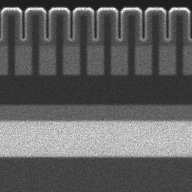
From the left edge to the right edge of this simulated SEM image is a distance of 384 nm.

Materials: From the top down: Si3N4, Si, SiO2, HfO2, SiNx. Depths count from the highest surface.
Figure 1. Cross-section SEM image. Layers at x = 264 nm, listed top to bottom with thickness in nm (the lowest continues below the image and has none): Si3N4 14, Si 180, SiO2 32, HfO2 72, SiNx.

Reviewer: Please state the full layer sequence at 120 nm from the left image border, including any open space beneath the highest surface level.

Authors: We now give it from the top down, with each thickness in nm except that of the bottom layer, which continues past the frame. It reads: Si3N4 14, Si 180, SiO2 32, HfO2 72, SiNx